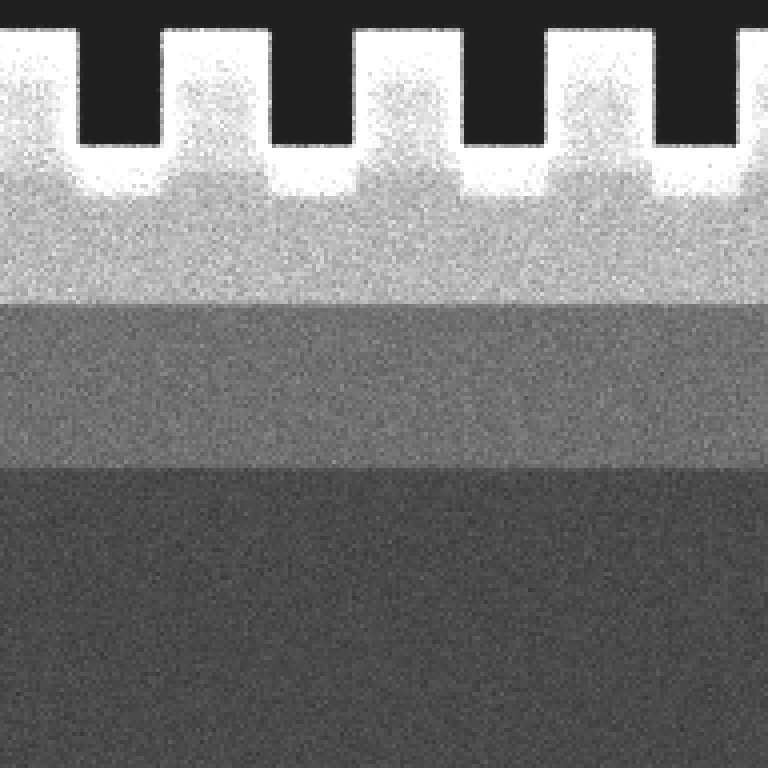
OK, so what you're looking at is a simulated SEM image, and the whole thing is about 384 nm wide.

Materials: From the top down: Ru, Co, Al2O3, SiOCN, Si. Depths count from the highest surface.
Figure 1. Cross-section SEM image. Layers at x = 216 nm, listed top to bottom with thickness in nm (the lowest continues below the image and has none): Ru 24, Co 46, Al2O3 66, SiOCN 82, Si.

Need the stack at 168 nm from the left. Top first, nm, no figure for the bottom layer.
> empty 58, Ru 24, Al2O3 54, SiOCN 82, Si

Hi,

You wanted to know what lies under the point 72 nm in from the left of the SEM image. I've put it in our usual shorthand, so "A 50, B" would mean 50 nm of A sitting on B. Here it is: empty 58, Ru 24, Al2O3 54, SiOCN 82, Si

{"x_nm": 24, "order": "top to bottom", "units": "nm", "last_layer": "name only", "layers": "Ru 24, Co 46, Al2O3 66, SiOCN 82, Si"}